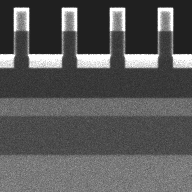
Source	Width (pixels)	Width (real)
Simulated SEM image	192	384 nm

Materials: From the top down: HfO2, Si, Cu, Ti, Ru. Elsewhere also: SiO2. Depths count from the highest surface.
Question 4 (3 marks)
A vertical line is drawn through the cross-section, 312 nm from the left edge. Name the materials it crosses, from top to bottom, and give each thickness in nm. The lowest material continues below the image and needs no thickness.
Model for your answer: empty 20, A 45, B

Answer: empty 94, HfO2 26, Si 60, Cu 36, Ti 78, Ru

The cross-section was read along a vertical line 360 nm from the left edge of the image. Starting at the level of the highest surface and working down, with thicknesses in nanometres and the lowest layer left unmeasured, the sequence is empty 94, HfO2 26, Si 60, Cu 36, Ti 78, Ru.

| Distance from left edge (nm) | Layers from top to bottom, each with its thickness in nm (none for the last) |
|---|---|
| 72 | empty 94, HfO2 26, Si 60, Cu 36, Ti 78, Ru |